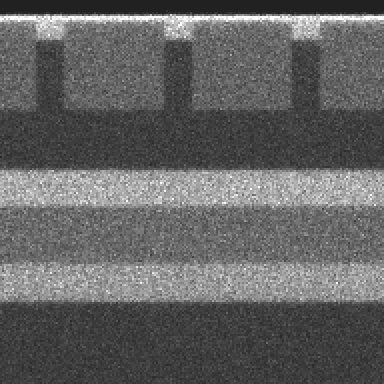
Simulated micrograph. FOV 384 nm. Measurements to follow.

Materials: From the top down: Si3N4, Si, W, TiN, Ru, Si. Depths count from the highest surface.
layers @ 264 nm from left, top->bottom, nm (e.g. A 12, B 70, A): Si3N4 94, Si 60, W 36, TiN 58, Ru 38, Si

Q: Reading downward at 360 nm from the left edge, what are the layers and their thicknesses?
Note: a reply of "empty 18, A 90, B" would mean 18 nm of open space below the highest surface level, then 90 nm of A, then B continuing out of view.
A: Si3N4 94, Si 60, W 36, TiN 58, Ru 38, Si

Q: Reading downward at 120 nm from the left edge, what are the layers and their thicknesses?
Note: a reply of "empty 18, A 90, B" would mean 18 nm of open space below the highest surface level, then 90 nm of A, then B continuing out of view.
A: Si3N4 94, Si 60, W 36, TiN 58, Ru 38, Si